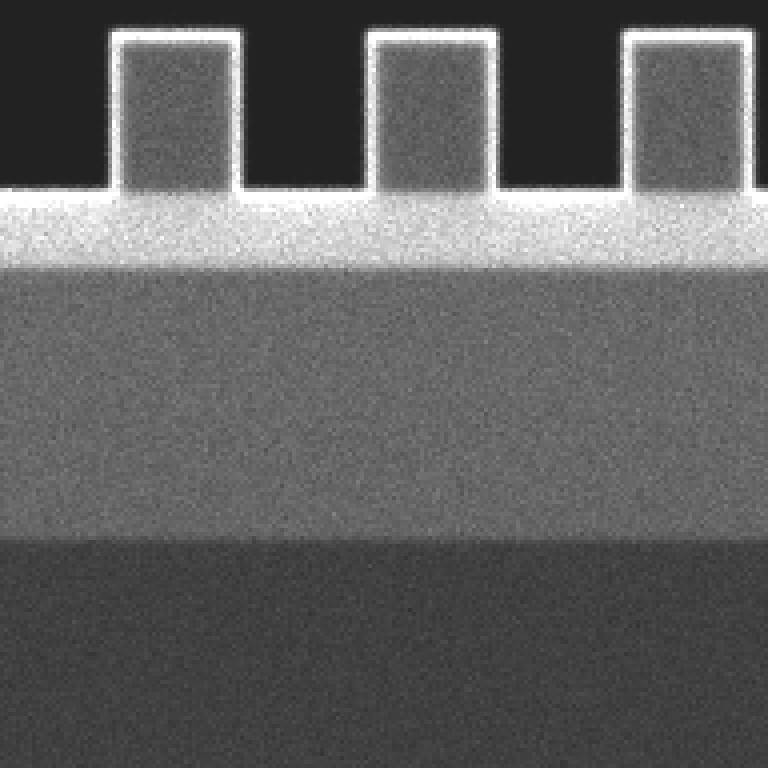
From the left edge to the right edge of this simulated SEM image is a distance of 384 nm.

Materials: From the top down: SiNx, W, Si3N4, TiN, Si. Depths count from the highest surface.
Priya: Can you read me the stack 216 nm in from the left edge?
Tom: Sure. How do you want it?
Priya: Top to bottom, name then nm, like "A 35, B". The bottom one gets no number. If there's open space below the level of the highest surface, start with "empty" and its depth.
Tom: SiNx 80, W 38, Si3N4 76, TiN 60, Si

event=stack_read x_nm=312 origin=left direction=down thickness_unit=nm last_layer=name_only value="SiNx 80, W 38, Si3N4 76, TiN 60, Si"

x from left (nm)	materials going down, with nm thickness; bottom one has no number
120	empty 80, W 38, Si3N4 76, TiN 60, Si